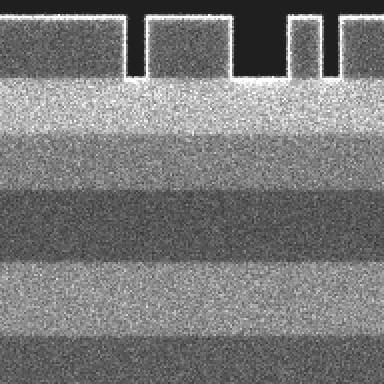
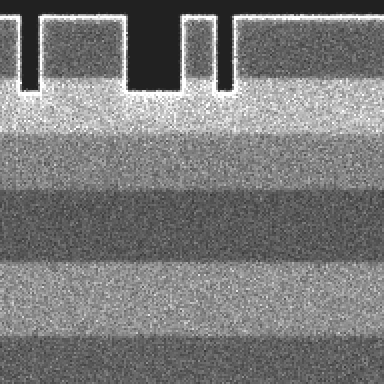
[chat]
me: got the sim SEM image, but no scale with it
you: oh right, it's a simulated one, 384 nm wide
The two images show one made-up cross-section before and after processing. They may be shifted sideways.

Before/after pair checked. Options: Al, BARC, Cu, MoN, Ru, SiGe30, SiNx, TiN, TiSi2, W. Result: removed W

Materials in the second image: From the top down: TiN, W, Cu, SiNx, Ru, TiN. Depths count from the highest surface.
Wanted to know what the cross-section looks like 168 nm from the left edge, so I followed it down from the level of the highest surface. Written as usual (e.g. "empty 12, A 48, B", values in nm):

empty 76, W 42, Cu 56, SiNx 72, Ru 74, TiN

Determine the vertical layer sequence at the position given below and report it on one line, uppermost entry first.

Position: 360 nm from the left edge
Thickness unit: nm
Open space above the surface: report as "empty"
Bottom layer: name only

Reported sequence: TiN 62, W 56, Cu 56, SiNx 72, Ru 74, TiN